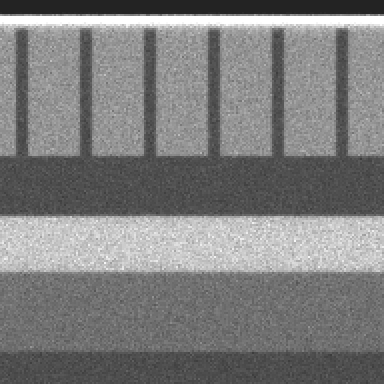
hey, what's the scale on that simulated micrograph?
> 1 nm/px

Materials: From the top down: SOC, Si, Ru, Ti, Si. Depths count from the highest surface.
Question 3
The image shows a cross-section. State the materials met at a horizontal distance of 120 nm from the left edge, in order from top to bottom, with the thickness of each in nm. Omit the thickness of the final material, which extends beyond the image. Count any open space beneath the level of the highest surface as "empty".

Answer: SOC 140, Si 60, Ru 56, Ti 80, Si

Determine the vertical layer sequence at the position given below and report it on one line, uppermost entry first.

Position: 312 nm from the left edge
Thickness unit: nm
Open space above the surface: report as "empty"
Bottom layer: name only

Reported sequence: SOC 140, Si 60, Ru 56, Ti 80, Si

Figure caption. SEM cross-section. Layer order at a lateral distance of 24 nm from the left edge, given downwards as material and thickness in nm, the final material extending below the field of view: SOC 12, Si 188, Ru 56, Ti 80, Si